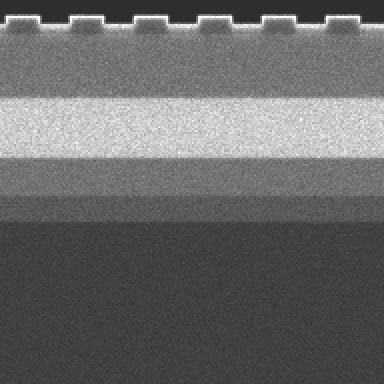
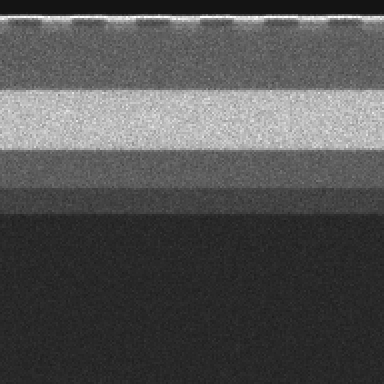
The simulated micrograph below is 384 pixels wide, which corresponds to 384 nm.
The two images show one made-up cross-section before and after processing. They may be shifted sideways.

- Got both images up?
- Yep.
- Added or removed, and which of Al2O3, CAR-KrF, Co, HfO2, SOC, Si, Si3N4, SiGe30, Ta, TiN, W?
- removed, TiN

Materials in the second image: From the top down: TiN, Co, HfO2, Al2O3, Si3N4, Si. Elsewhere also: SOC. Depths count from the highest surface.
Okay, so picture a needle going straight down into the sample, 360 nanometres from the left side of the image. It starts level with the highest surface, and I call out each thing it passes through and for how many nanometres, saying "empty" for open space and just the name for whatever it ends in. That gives TiN 10, Co 64, HfO2 60, Al2O3 38, Si3N4 26, Si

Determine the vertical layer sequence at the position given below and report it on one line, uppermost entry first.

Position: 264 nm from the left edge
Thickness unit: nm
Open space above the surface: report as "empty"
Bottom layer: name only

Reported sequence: TiN 10, Co 64, HfO2 60, Al2O3 38, Si3N4 26, Si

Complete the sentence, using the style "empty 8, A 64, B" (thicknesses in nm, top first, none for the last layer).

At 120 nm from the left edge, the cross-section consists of SOC 10, Co 64, HfO2 60, Al2O3 38, Si3N4 26, Si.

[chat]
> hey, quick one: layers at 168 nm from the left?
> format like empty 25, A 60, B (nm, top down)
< TiN 10, Co 64, HfO2 60, Al2O3 38, Si3N4 26, Si